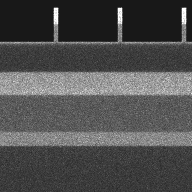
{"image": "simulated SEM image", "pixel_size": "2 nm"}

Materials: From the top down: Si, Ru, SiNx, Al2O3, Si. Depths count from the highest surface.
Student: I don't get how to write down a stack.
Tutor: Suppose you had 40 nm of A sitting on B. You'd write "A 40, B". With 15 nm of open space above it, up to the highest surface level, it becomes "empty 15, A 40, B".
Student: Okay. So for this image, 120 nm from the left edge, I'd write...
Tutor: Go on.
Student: empty 68, Si 60, Ru 46, SiNx 74, Al2O3 28, Si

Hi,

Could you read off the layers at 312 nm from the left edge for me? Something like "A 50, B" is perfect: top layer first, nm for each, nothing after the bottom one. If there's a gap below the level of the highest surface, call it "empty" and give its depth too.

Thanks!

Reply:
empty 68, Si 60, Ru 46, SiNx 74, Al2O3 28, Si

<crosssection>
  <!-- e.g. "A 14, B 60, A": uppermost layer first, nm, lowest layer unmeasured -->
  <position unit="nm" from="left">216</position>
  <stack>empty 68, Si 60, Ru 46, SiNx 74, Al2O3 28, Si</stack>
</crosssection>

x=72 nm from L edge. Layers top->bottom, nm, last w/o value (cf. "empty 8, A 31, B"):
empty 68, Si 60, Ru 46, SiNx 74, Al2O3 28, Si